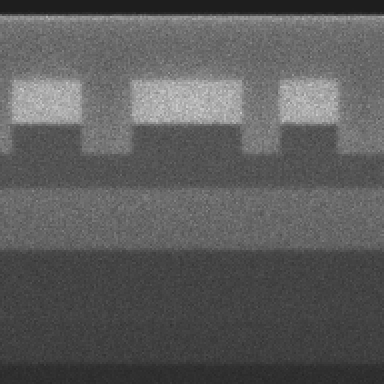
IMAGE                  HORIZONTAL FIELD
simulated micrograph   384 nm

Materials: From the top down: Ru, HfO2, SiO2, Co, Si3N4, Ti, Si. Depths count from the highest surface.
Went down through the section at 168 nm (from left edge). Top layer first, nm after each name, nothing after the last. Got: Ru 64, HfO2 44, SiO2 64, Co 62, Si3N4 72, Ti 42, Si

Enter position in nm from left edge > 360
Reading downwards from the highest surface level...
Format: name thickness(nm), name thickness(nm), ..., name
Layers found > Ru 138, SiO2 34, Co 62, Si3N4 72, Ti 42, Si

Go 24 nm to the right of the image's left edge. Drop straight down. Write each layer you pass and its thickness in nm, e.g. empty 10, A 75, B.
Ru 64, HfO2 44, SiO2 64, Co 62, Si3N4 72, Ti 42, Si